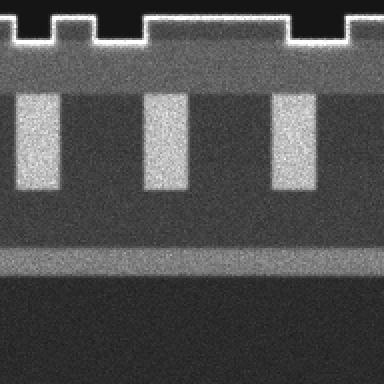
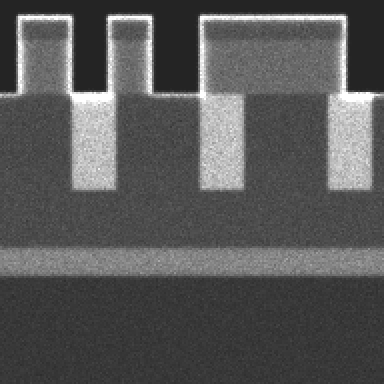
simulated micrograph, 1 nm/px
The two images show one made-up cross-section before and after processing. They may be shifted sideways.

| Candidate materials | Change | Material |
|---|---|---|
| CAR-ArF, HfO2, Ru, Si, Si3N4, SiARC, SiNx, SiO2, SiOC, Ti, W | removed | SiO2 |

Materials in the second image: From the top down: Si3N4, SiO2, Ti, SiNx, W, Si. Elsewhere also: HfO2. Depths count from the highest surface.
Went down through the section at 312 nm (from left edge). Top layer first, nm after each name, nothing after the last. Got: Si3N4 24, SiO2 54, Ti 70, SiNx 84, W 28, Si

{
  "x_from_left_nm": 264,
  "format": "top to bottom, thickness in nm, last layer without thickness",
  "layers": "Si3N4 24, SiO2 54, Ti 70, SiNx 84, W 28, Si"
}